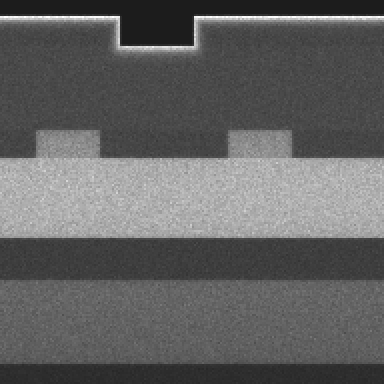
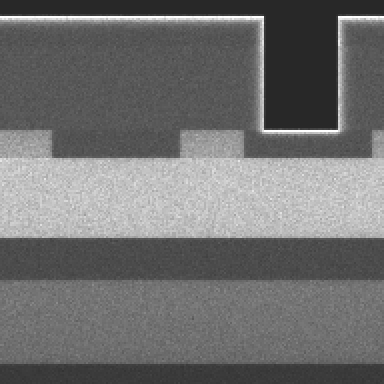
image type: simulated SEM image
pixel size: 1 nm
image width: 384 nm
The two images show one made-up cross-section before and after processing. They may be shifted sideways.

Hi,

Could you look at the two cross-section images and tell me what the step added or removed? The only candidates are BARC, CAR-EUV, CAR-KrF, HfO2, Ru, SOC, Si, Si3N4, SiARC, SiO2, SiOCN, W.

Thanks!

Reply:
removed SOC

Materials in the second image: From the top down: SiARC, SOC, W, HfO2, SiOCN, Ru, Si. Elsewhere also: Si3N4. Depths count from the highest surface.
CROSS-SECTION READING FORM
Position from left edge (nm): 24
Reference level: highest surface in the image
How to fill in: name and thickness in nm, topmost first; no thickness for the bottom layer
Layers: SiARC 30, SOC 84, W 28, HfO2 80, SiOCN 42, Ru 84, Si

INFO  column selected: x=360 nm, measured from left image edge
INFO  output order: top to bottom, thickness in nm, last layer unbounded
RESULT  SiARC 30, SOC 84, Si3N4 28, HfO2 80, SiOCN 42, Ru 84, Si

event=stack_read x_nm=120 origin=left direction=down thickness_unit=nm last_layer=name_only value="SiARC 30, SOC 84, Si3N4 28, HfO2 80, SiOCN 42, Ru 84, Si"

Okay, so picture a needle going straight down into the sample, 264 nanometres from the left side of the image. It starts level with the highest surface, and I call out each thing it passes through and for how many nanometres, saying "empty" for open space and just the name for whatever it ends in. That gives empty 114, Si3N4 28, HfO2 80, SiOCN 42, Ru 84, Si